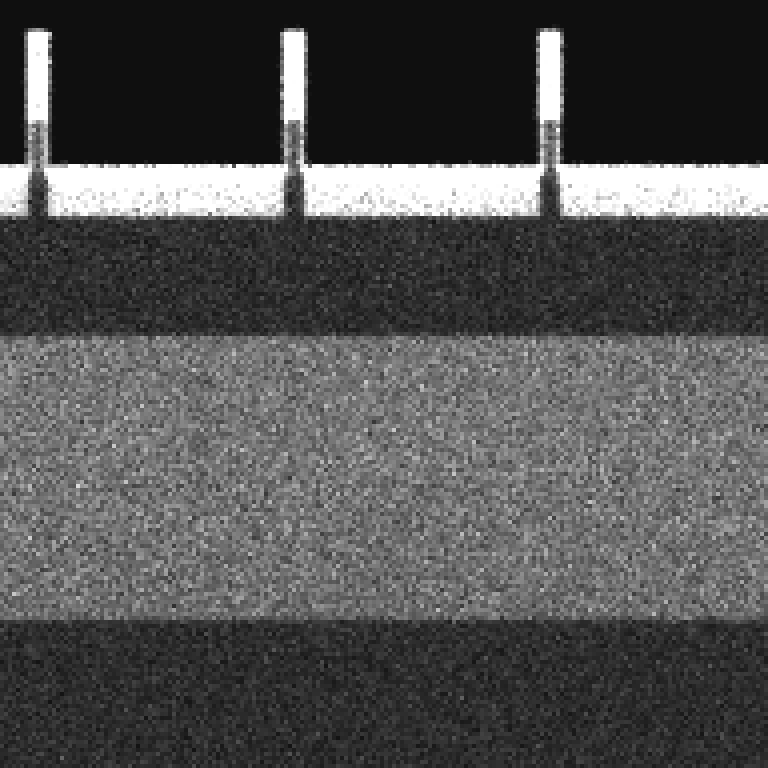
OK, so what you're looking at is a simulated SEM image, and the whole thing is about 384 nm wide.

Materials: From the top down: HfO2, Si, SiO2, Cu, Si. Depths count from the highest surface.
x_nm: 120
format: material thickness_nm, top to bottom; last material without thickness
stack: empty 68, HfO2 24, Si 60, SiO2 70, Cu 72, Si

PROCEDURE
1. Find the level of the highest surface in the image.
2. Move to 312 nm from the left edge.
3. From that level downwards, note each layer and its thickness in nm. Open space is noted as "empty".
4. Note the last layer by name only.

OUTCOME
empty 68, HfO2 24, Si 60, SiO2 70, Cu 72, Si